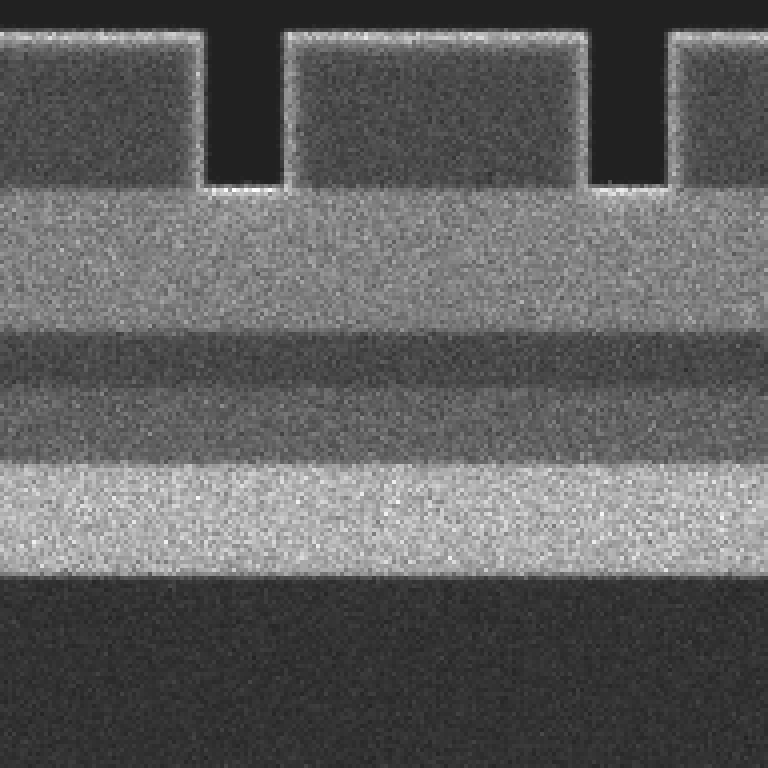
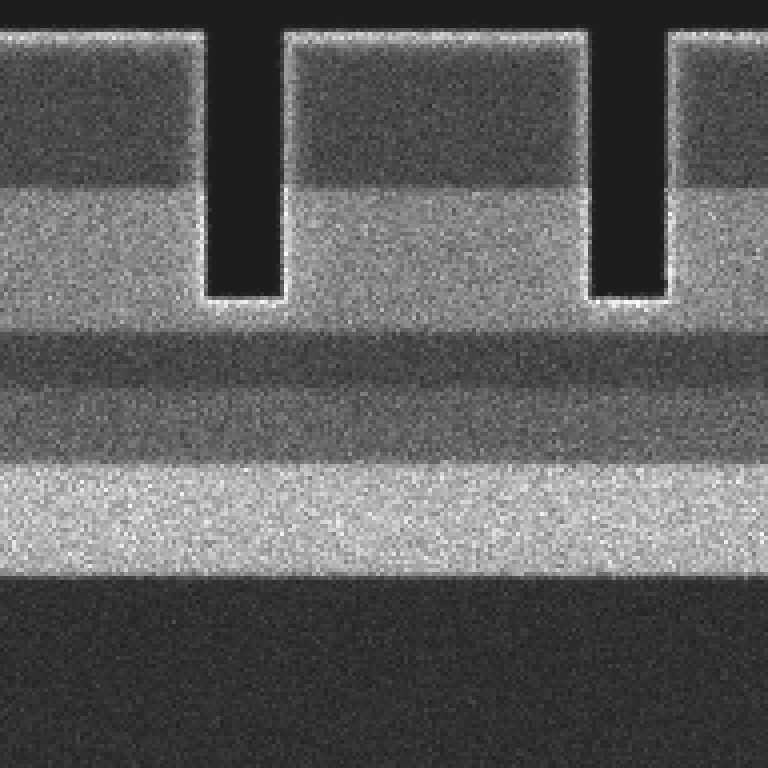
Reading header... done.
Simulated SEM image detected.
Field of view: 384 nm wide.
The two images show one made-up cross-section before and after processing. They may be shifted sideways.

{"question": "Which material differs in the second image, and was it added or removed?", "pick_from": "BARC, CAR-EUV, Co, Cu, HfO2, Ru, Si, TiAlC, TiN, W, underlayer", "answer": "W, removed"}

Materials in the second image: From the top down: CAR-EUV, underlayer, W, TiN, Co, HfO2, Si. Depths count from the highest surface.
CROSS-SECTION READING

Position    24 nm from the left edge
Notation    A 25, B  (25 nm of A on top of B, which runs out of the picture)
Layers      CAR-EUV 32, underlayer 46, W 72, TiN 28, Co 38, HfO2 56, Si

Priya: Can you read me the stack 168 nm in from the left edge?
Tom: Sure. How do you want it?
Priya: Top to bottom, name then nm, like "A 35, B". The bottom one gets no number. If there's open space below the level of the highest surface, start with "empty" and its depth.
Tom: CAR-EUV 32, underlayer 46, W 72, TiN 28, Co 38, HfO2 56, Si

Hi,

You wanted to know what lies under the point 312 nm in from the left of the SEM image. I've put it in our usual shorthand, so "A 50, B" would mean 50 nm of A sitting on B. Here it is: empty 134, W 16, TiN 28, Co 38, HfO2 56, Si